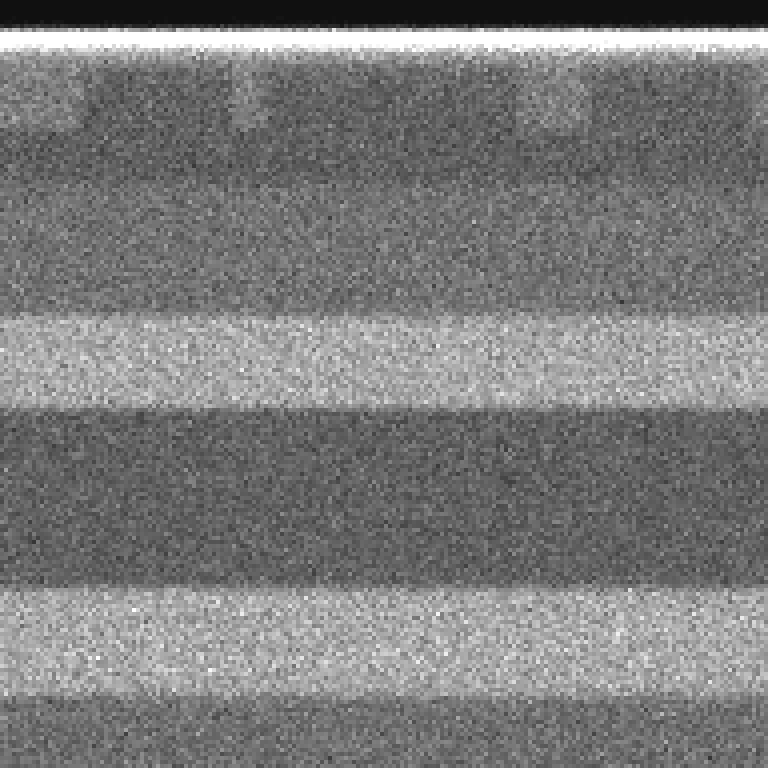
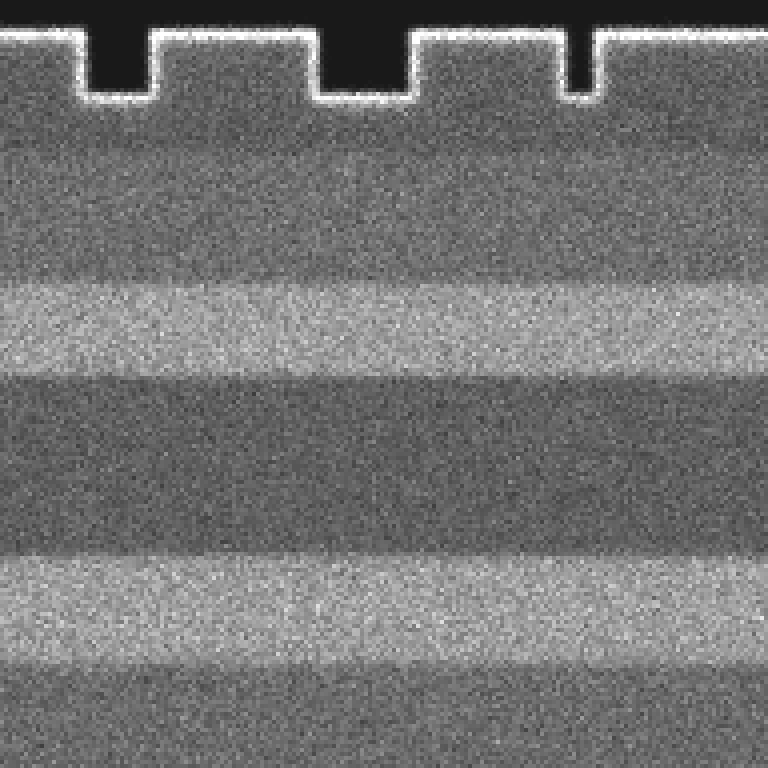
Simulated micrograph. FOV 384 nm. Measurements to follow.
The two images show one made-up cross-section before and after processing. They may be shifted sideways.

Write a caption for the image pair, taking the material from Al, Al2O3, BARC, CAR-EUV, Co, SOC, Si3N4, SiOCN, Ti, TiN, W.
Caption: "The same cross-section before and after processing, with SOC removed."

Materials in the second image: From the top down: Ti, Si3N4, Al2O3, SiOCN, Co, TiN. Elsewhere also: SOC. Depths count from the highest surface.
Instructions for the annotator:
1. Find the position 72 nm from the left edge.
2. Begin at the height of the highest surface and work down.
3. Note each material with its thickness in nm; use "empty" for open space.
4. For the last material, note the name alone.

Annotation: empty 32, Ti 28, Si3N4 66, Al2O3 46, SiOCN 90, Co 54, TiN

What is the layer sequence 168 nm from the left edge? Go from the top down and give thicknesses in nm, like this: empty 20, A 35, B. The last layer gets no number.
empty 32, Ti 28, Si3N4 66, Al2O3 46, SiOCN 90, Co 54, TiN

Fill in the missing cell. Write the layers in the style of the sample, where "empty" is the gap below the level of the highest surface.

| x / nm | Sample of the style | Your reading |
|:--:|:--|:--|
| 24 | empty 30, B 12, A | Ti 60, Si3N4 66, Al2O3 46, SiOCN 90, Co 54, TiN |